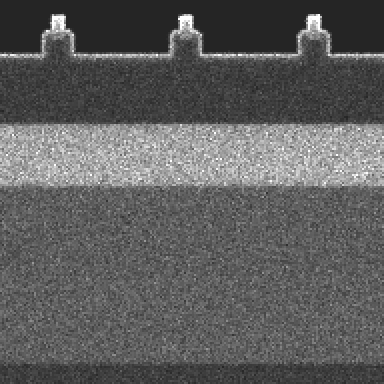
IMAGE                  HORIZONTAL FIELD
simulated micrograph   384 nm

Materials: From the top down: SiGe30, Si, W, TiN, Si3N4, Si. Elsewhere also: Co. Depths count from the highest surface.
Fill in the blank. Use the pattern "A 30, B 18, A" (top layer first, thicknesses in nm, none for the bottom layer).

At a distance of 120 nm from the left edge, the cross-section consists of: empty 38, SiGe30 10, Si 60, W 62, TiN 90, Si3N4 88, Si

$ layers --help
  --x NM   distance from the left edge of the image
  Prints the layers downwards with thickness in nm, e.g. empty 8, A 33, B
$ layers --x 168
empty 38, SiGe30 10, Si 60, W 62, TiN 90, Si3N4 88, Si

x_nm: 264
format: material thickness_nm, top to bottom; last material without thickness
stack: empty 38, SiGe30 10, Si 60, W 62, TiN 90, Si3N4 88, Si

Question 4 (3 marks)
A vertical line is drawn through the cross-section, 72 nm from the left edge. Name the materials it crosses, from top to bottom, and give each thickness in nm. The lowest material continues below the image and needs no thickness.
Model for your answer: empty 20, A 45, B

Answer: empty 18, SiGe30 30, Si 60, W 62, TiN 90, Si3N4 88, Si